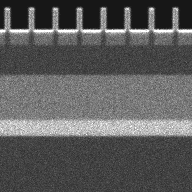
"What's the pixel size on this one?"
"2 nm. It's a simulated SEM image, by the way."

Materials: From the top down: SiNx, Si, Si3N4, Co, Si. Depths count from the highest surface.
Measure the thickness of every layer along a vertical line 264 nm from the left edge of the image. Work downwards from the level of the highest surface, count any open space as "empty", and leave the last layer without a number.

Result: empty 44, SiNx 30, Si 60, Si3N4 90, Co 32, Si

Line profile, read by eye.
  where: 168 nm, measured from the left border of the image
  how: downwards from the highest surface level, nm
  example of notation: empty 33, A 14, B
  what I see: empty 44, SiNx 30, Si 60, Si3N4 90, Co 32, Si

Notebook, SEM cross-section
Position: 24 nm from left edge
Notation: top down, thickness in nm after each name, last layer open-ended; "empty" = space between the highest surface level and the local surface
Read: empty 44, SiNx 30, Si 60, Si3N4 90, Co 32, Si